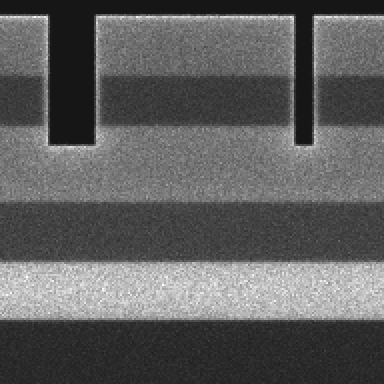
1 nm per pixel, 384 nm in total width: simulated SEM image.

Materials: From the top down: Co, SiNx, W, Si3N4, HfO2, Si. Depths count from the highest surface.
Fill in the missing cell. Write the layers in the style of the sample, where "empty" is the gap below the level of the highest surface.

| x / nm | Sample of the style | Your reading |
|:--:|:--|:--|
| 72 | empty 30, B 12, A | empty 130, W 56, Si3N4 60, HfO2 58, Si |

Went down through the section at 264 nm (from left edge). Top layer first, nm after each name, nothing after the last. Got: Co 60, SiNx 50, W 76, Si3N4 60, HfO2 58, Si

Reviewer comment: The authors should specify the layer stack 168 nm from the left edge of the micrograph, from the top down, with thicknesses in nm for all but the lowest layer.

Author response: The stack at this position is Co 60, SiNx 50, W 76, Si3N4 60, HfO2 58, Si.